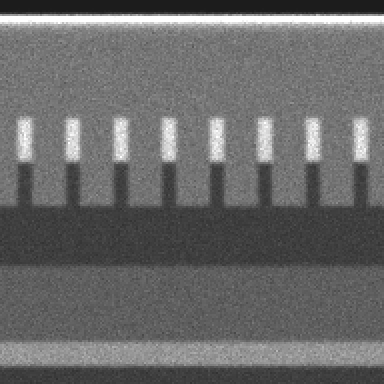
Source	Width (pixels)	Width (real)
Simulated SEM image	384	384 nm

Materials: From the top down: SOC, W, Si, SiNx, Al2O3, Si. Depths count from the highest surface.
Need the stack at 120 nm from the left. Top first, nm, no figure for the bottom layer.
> SOC 102, W 44, Si 104, SiNx 76, Al2O3 24, Si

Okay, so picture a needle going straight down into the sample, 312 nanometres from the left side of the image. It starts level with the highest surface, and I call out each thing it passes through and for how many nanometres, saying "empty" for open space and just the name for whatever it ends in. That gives SOC 102, W 44, Si 104, SiNx 76, Al2O3 24, Si